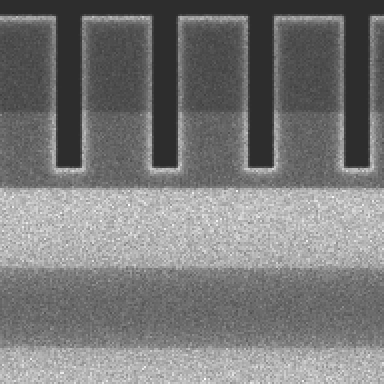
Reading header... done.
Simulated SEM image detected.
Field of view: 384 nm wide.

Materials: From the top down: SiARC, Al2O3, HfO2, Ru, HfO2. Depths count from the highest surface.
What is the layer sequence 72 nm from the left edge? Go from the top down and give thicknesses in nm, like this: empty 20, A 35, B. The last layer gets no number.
empty 152, Al2O3 20, HfO2 80, Ru 80, HfO2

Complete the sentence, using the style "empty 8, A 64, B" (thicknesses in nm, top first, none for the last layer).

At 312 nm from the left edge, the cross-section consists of SiARC 96, Al2O3 76, HfO2 80, Ru 80, HfO2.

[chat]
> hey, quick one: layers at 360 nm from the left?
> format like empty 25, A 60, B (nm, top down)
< empty 152, Al2O3 20, HfO2 80, Ru 80, HfO2